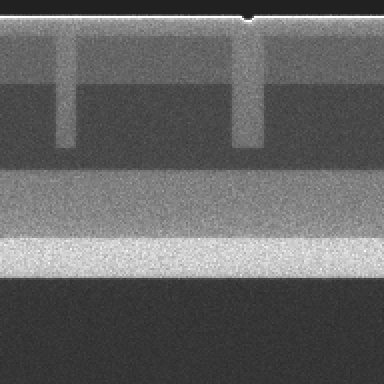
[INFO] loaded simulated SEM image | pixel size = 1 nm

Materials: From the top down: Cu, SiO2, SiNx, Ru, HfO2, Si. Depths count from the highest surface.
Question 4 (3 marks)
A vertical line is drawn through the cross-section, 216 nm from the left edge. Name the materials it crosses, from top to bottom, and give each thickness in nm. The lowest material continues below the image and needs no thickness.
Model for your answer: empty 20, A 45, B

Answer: Cu 20, SiO2 48, SiNx 86, Ru 68, HfO2 40, Si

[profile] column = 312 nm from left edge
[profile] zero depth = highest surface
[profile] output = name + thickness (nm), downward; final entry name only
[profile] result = Cu 20, SiO2 48, SiNx 86, Ru 68, HfO2 40, Si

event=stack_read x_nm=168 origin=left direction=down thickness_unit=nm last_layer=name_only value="Cu 20, SiO2 48, SiNx 86, Ru 68, HfO2 40, Si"